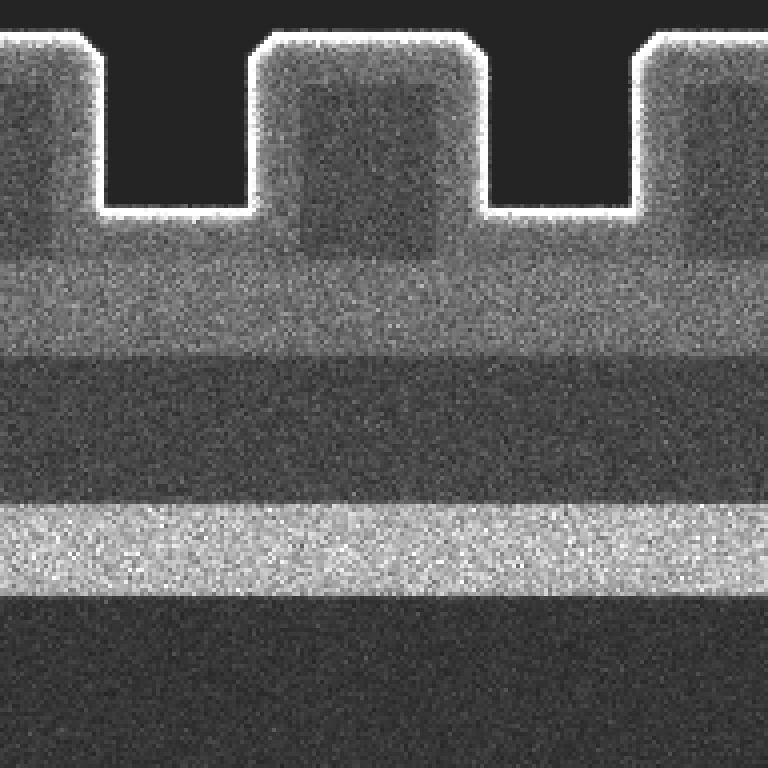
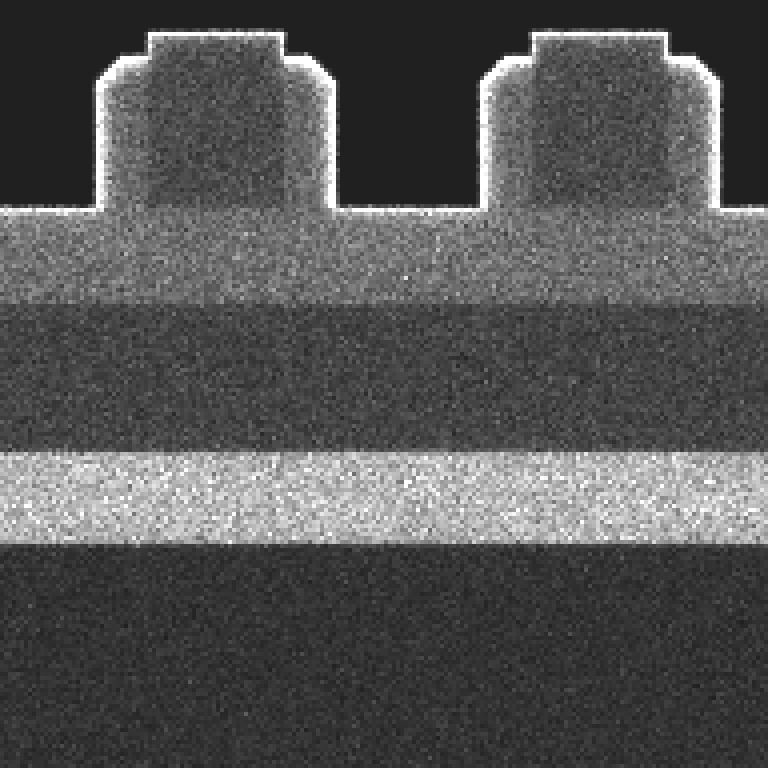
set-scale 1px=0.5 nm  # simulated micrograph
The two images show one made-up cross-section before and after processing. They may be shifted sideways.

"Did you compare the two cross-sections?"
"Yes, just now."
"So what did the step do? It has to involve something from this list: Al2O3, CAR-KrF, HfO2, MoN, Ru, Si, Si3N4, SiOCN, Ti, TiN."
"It removed Al2O3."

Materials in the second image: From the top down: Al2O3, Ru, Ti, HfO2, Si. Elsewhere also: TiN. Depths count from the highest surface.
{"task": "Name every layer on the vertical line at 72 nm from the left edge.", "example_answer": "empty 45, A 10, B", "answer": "empty 12, Al2O3 76, Ru 48, Ti 74, HfO2 46, Si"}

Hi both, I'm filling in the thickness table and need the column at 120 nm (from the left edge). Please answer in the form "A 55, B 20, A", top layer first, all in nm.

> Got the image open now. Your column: TiN 88, Ru 48, Ti 74, HfO2 46, Si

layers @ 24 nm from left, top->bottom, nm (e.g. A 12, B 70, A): empty 88, Ru 48, Ti 74, HfO2 46, Si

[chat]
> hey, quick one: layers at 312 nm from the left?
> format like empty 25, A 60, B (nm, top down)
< TiN 88, Ru 48, Ti 74, HfO2 46, Si